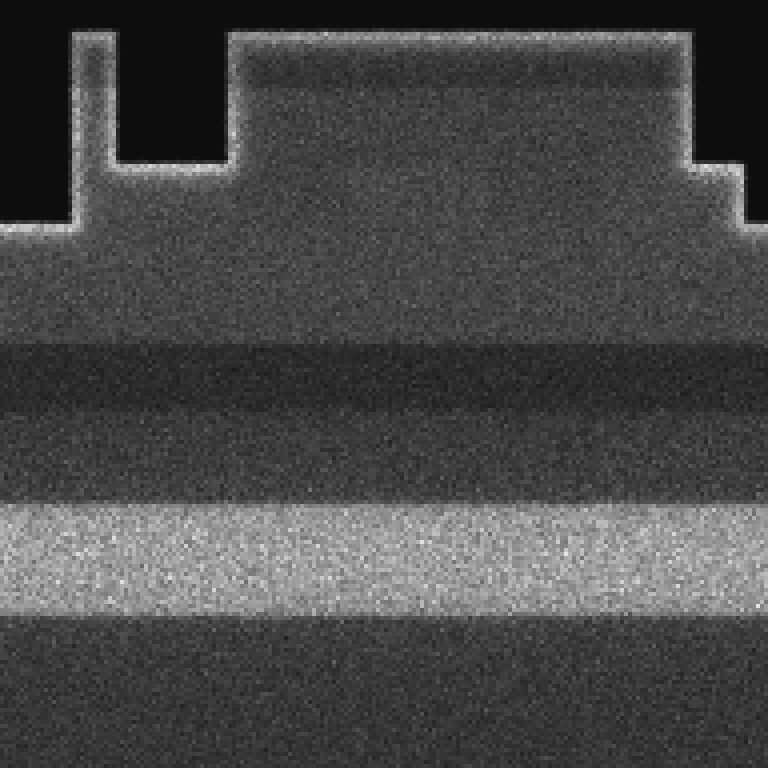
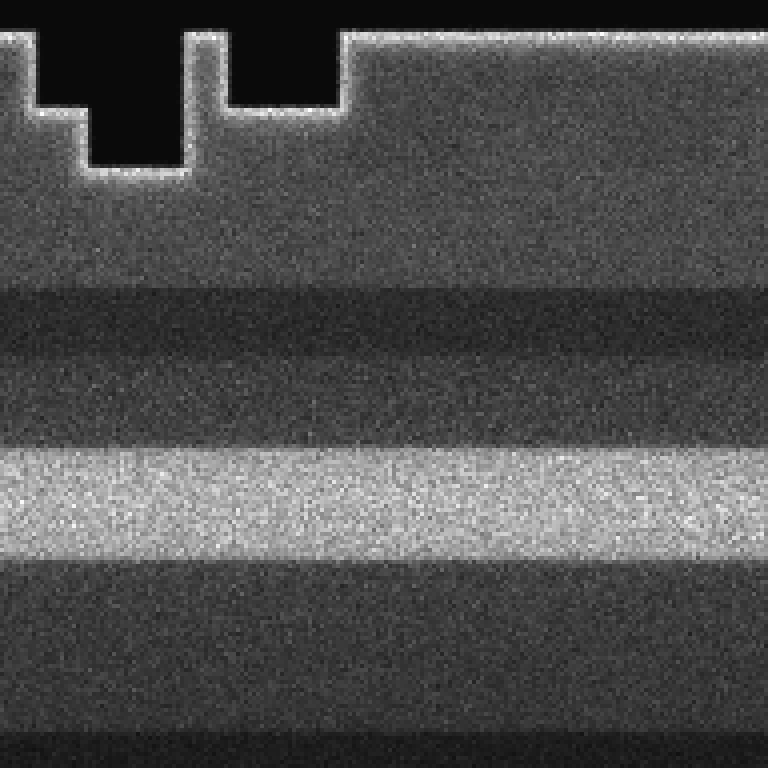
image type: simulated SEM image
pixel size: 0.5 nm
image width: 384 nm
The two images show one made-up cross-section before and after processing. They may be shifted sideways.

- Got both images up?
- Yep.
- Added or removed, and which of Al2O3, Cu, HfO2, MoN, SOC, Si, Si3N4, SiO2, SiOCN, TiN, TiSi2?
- removed, SOC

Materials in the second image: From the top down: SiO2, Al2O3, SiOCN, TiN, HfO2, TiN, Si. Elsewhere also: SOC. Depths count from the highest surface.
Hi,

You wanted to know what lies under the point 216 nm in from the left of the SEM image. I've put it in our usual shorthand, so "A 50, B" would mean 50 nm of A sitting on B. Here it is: SiO2 68, Al2O3 60, SiOCN 34, TiN 46, HfO2 56, TiN 86, Si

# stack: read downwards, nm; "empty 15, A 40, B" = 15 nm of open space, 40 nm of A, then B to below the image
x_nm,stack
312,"SiO2 68, Al2O3 60, SiOCN 34, TiN 46, HfO2 56, TiN 86, Si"